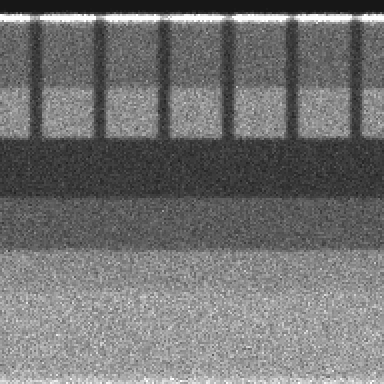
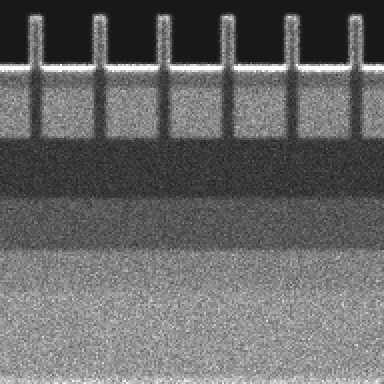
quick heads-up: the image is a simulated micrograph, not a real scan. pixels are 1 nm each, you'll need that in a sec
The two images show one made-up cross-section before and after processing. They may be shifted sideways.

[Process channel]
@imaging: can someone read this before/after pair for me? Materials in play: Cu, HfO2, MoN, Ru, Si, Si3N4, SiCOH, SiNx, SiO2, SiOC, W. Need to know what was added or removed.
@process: Si3N4 removed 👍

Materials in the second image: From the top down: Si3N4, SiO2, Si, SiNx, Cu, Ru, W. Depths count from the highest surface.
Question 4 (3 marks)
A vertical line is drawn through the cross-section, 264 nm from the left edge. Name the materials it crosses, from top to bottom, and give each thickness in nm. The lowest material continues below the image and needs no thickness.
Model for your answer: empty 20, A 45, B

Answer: empty 50, Si3N4 22, SiO2 50, Si 60, SiNx 52, Cu 40, Ru 88, W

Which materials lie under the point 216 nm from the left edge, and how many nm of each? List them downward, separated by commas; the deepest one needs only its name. empty 50, Si3N4 22, SiO2 50, Si 60, SiNx 52, Cu 40, Ru 88, W